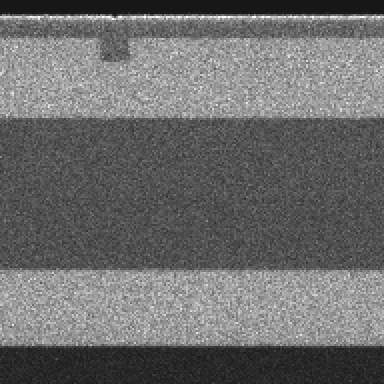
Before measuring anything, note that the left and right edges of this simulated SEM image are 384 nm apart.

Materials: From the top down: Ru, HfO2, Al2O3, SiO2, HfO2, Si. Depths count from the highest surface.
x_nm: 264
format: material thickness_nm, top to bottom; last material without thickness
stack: Ru 22, HfO2 80, Al2O3 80, SiO2 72, HfO2 76, Si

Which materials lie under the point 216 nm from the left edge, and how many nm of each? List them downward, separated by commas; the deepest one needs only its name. Ru 22, HfO2 80, Al2O3 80, SiO2 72, HfO2 76, Si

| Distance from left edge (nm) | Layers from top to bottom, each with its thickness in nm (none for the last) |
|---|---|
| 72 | Ru 22, HfO2 80, Al2O3 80, SiO2 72, HfO2 76, Si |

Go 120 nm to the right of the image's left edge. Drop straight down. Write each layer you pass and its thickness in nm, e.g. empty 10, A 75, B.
Ru 46, HfO2 56, Al2O3 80, SiO2 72, HfO2 76, Si